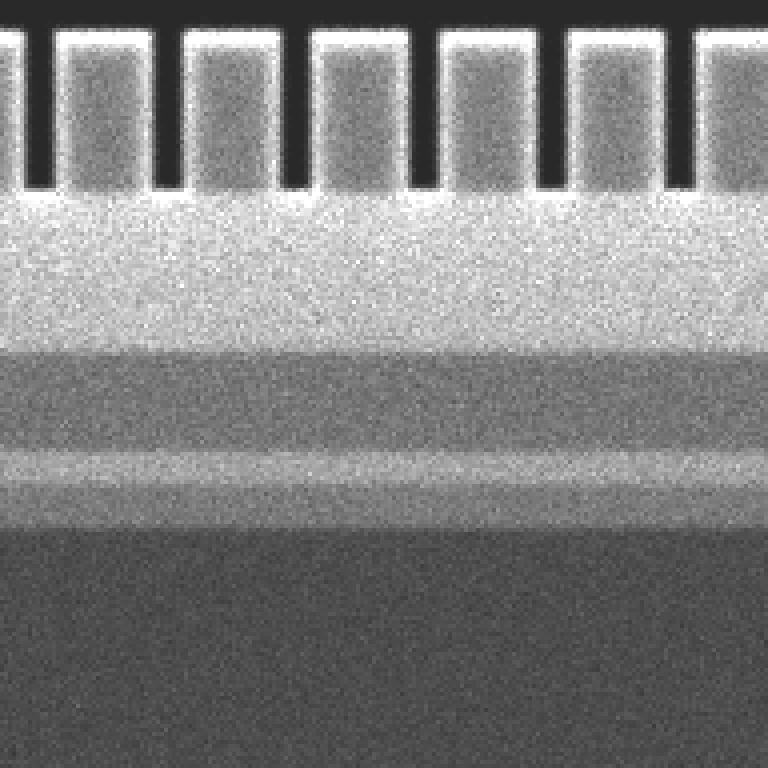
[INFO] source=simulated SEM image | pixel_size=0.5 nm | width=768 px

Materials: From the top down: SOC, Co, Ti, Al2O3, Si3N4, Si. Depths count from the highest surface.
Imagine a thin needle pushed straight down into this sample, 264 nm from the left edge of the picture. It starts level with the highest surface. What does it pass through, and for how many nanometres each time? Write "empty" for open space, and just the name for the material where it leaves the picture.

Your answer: SOC 80, Co 80, Ti 50, Al2O3 16, Si3N4 22, Si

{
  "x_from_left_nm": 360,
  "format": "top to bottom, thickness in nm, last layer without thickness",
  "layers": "SOC 80, Co 80, Ti 50, Al2O3 16, Si3N4 22, Si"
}